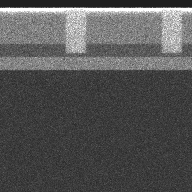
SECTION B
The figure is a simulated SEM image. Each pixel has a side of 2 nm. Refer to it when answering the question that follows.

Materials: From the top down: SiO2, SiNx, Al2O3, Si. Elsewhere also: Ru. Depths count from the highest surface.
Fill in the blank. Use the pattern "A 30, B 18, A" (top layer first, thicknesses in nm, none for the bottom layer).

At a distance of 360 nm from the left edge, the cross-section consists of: Ru 90, SiNx 8, Al2O3 26, Si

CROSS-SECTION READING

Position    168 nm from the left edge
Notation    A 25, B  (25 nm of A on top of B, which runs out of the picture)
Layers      Ru 90, SiNx 8, Al2O3 26, Si